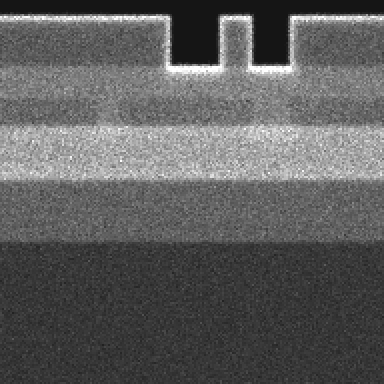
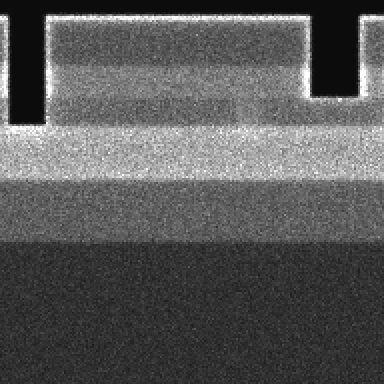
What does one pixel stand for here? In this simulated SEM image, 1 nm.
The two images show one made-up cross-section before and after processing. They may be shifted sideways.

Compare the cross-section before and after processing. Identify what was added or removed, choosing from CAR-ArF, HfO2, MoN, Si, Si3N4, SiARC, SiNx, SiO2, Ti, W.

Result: SiO2 removed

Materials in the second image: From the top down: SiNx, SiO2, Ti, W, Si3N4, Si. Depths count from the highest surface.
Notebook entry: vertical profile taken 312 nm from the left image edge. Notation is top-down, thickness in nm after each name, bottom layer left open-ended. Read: empty 82, Ti 28, W 54, Si3N4 62, Si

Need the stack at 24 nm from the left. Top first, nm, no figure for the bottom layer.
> empty 110, W 54, Si3N4 62, Si